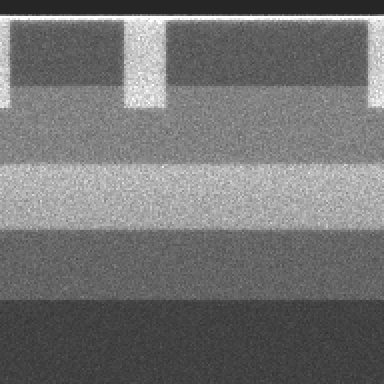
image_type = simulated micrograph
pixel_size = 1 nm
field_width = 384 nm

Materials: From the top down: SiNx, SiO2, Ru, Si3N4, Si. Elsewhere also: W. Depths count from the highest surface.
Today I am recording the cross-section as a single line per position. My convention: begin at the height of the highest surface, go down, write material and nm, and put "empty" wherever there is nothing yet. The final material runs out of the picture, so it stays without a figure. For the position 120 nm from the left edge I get SiNx 70, SiO2 78, Ru 66, Si3N4 70, Si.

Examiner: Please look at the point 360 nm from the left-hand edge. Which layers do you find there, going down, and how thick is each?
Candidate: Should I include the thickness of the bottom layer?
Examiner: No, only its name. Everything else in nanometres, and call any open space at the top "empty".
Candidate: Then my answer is SiNx 70, SiO2 78, Ru 66, Si3N4 70, Si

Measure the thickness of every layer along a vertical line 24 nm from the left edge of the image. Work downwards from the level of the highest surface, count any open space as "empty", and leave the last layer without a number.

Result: SiNx 70, SiO2 78, Ru 66, Si3N4 70, Si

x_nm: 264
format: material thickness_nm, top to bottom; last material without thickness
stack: SiNx 70, SiO2 78, Ru 66, Si3N4 70, Si